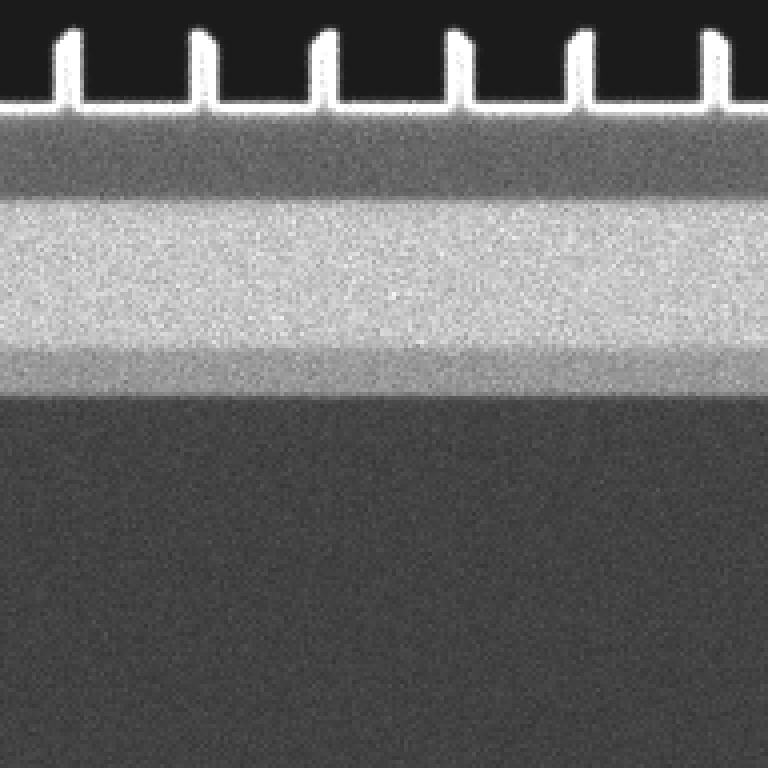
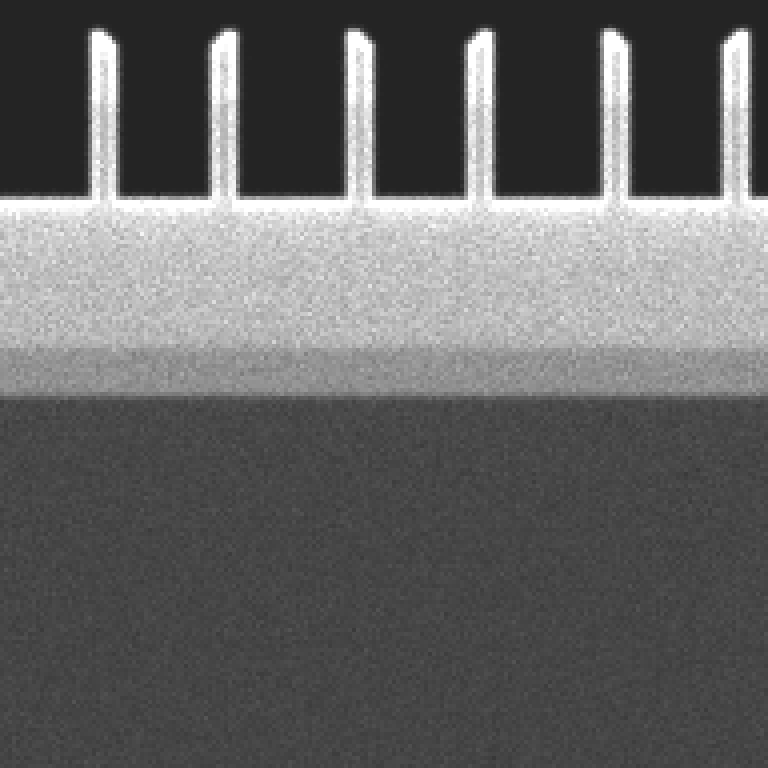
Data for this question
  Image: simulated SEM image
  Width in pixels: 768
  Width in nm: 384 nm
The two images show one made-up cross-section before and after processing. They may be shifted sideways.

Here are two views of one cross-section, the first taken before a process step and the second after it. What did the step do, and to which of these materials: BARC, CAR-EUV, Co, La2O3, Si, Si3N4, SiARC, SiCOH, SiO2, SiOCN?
It removed SiOCN.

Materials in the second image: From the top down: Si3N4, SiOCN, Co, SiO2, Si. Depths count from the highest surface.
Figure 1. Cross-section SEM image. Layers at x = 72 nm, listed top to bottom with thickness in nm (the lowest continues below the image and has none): empty 84, Co 74, SiO2 24, Si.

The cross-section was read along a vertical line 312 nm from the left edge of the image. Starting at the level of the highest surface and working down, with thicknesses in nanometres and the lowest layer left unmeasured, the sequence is empty 6, Si3N4 30, SiOCN 48, Co 74, SiO2 24, Si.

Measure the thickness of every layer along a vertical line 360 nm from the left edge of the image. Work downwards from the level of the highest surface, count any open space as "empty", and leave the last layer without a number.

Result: empty 84, Co 74, SiO2 24, Si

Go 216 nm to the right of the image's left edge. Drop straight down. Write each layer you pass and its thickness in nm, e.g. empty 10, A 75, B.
empty 84, Co 74, SiO2 24, Si